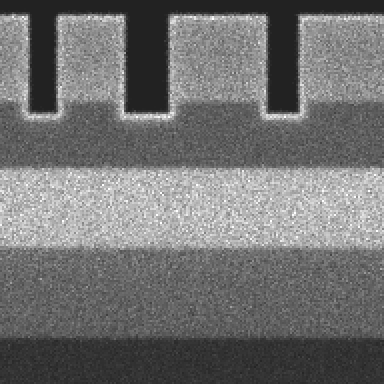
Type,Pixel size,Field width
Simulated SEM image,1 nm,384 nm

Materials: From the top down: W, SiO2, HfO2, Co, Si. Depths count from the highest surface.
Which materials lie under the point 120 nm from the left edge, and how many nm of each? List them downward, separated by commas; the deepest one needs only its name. W 86, SiO2 66, HfO2 80, Co 90, Si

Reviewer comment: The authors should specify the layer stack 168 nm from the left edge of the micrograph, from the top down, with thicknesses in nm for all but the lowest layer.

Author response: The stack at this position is empty 98, SiO2 54, HfO2 80, Co 90, Si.